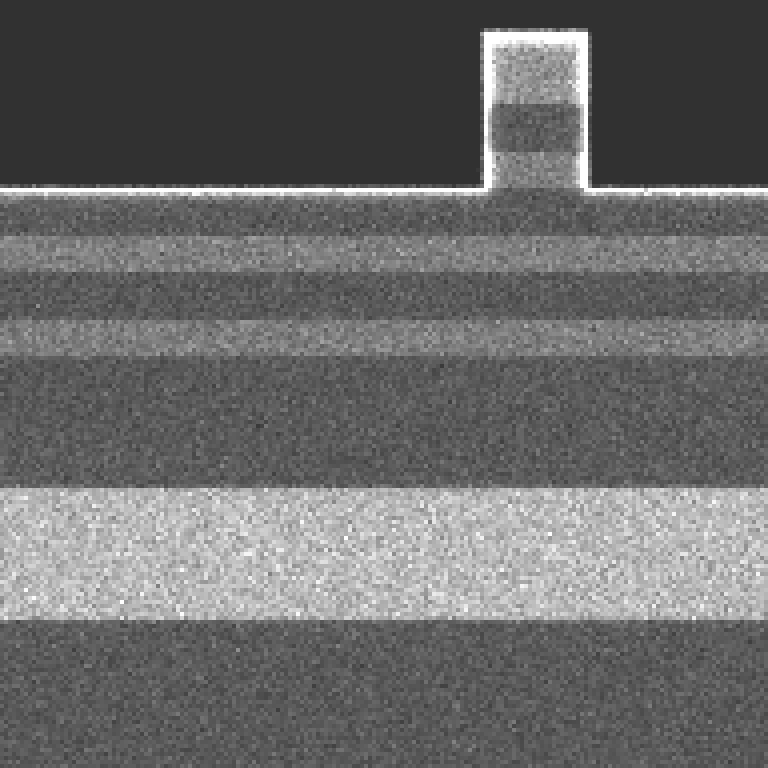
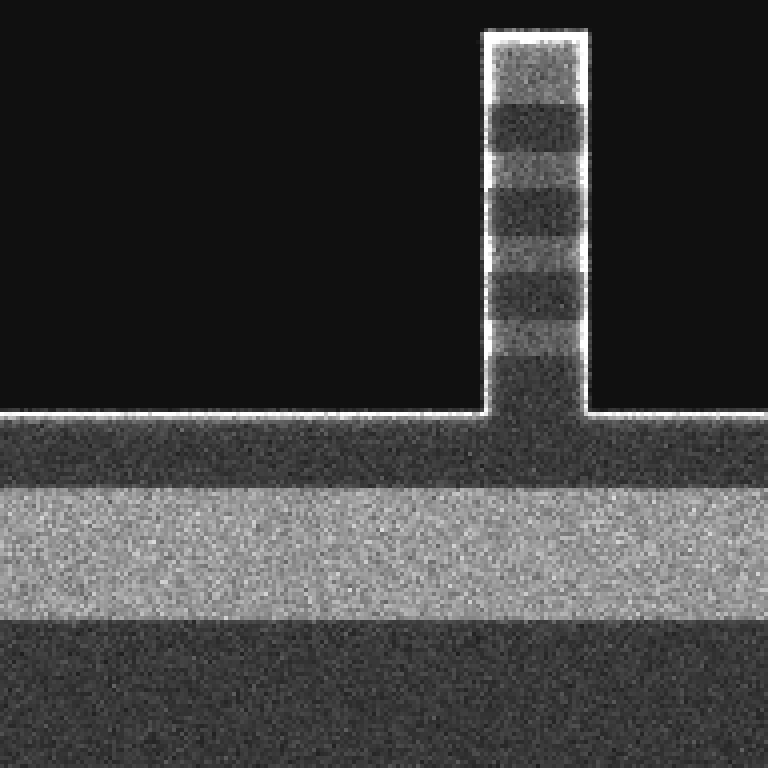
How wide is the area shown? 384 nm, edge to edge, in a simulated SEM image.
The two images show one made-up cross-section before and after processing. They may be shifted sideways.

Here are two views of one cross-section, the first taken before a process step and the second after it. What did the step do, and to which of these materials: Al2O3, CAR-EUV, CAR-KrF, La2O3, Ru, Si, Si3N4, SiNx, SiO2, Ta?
It removed Si and SiNx.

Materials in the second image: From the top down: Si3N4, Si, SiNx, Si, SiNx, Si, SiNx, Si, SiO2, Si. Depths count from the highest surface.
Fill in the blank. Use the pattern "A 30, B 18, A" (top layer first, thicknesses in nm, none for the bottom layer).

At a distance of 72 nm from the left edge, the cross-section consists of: empty 190, Si 38, SiO2 66, Si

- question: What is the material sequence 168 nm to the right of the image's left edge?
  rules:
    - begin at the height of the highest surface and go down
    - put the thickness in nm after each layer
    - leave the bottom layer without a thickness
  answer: empty 190, Si 38, SiO2 66, Si